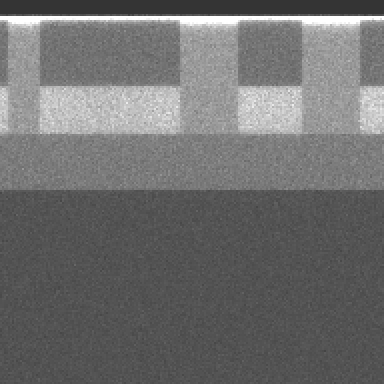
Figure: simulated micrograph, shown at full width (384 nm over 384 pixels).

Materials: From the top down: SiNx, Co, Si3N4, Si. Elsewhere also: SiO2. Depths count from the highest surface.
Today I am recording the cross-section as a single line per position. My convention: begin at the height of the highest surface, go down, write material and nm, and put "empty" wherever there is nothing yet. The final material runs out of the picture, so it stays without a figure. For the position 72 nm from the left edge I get SiNx 70, Co 48, Si3N4 56, Si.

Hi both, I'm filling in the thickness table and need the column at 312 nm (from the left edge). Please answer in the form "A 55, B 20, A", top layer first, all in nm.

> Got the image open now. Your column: SiO2 118, Si3N4 56, Si